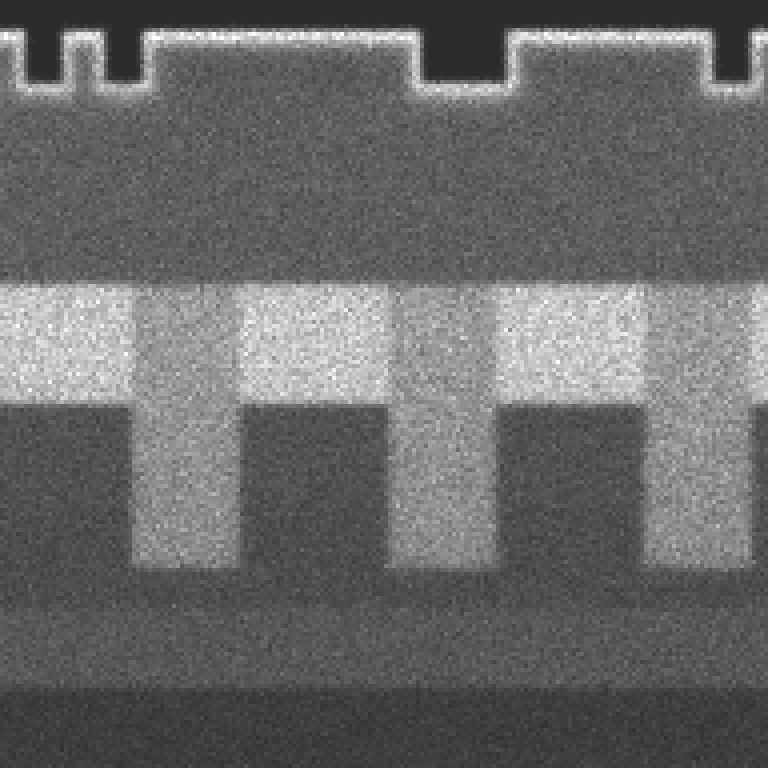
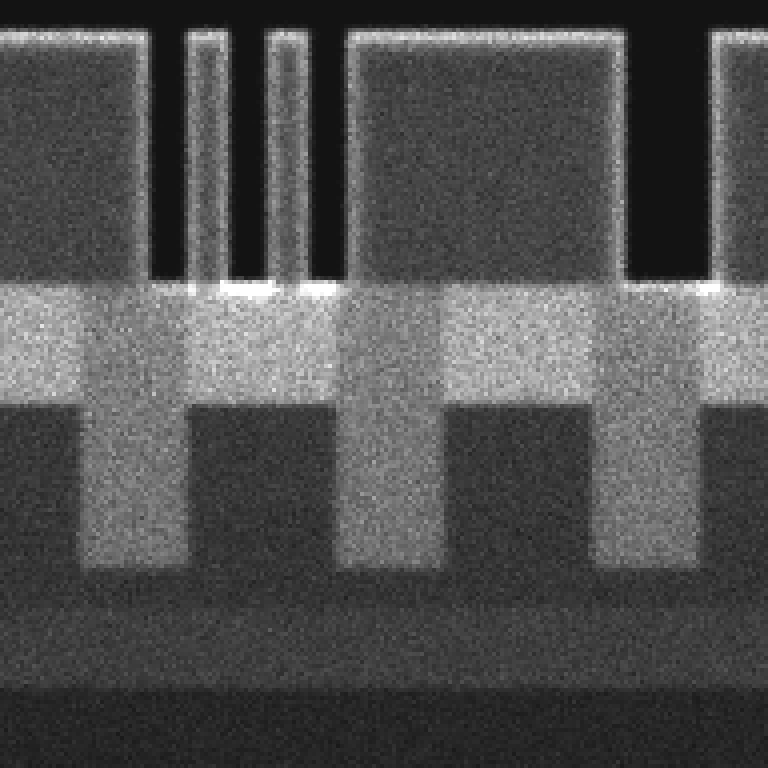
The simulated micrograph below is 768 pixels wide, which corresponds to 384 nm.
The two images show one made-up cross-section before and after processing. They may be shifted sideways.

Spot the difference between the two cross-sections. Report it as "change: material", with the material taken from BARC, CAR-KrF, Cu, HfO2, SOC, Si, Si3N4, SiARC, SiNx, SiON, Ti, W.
removed: SOC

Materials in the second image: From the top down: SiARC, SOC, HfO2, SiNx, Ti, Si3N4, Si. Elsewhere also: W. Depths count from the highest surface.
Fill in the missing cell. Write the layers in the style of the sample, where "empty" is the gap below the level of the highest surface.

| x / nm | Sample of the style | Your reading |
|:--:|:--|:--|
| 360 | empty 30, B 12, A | SiARC 26, SOC 100, HfO2 60, SiNx 52, Ti 50, Si3N4 40, Si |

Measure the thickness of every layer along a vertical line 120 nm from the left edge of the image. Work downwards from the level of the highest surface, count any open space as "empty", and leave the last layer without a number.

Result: empty 126, HfO2 60, SiNx 52, Ti 50, Si3N4 40, Si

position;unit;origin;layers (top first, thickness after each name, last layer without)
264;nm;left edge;SiARC 26, SOC 100, HfO2 60, SiNx 52, Ti 50, Si3N4 40, Si